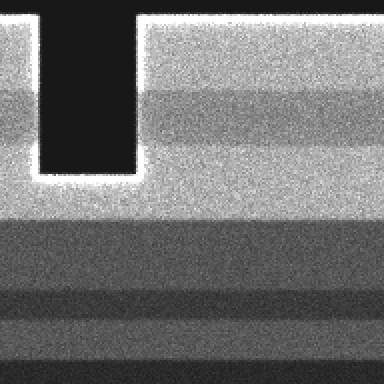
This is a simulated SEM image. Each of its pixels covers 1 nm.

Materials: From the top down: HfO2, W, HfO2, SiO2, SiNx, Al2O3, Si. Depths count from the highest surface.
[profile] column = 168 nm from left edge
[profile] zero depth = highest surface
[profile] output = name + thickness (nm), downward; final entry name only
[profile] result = HfO2 74, W 56, HfO2 74, SiO2 70, SiNx 30, Al2O3 40, Si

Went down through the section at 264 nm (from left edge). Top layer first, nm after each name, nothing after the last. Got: HfO2 74, W 56, HfO2 74, SiO2 70, SiNx 30, Al2O3 40, Si